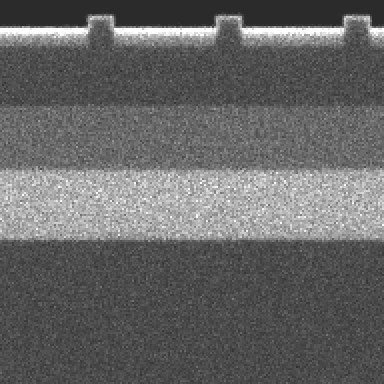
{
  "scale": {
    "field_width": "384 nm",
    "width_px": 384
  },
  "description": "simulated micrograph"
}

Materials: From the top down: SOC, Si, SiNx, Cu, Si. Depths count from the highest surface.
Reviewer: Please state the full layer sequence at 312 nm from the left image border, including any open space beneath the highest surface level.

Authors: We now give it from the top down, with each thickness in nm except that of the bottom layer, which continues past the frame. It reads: empty 12, SOC 18, Si 60, SiNx 64, Cu 70, Si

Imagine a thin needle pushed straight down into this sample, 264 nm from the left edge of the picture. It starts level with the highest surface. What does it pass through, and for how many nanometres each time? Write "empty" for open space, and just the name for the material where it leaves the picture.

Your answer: empty 12, SOC 18, Si 60, SiNx 64, Cu 70, Si